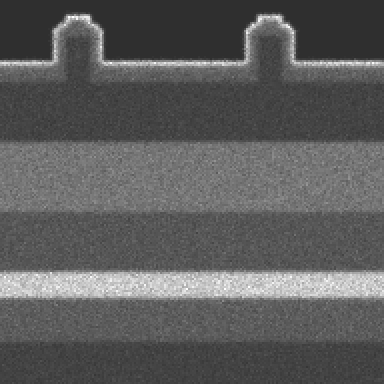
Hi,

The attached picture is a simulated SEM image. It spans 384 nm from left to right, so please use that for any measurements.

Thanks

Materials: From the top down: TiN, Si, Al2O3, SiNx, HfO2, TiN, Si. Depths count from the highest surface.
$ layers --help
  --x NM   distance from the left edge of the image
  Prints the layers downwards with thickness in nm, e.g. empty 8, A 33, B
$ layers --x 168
empty 46, TiN 20, Si 60, Al2O3 70, SiNx 60, HfO2 26, TiN 44, Si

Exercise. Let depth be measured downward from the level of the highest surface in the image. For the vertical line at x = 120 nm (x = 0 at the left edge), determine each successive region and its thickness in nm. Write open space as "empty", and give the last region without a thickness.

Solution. empty 46, TiN 20, Si 60, Al2O3 70, SiNx 60, HfO2 26, TiN 44, Si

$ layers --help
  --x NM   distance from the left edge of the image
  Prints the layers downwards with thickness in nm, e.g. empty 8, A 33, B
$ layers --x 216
empty 46, TiN 20, Si 60, Al2O3 70, SiNx 60, HfO2 26, TiN 44, Si